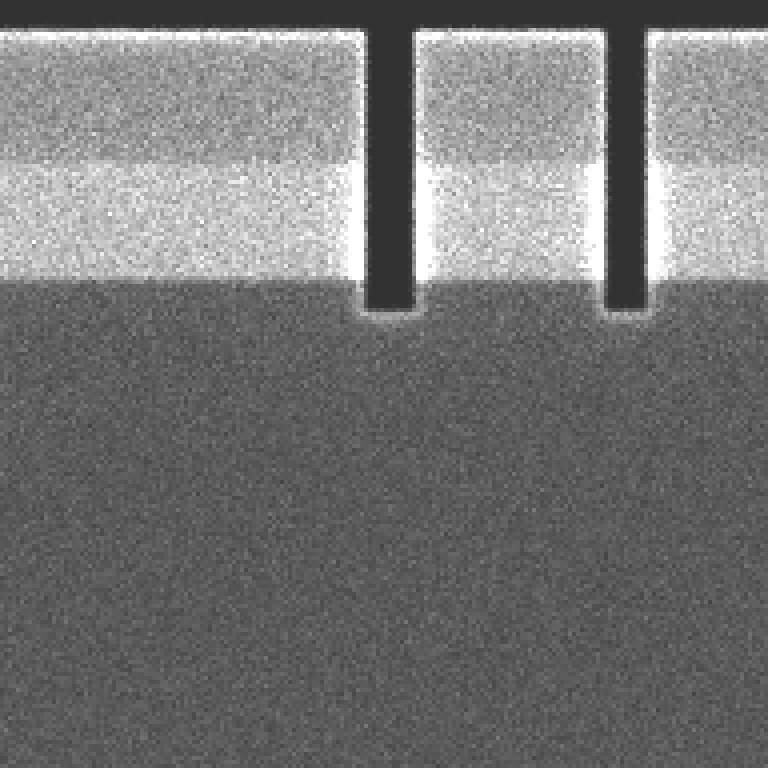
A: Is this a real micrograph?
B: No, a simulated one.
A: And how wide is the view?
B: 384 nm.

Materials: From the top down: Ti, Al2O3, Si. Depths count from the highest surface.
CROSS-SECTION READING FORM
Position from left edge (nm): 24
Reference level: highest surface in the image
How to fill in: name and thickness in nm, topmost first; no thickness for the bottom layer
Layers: Ti 66, Al2O3 58, Si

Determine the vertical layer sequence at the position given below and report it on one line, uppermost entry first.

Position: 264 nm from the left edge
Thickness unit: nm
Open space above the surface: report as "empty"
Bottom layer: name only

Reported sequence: Ti 66, Al2O3 58, Si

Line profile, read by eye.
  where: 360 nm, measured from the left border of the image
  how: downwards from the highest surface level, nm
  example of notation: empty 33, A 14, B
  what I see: Ti 66, Al2O3 58, Si